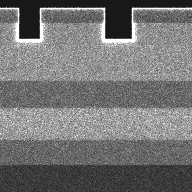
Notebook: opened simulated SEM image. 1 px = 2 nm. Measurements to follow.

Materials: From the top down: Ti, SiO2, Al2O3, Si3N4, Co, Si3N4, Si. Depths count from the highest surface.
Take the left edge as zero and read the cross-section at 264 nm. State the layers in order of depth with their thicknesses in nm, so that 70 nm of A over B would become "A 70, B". Ti 30, SiO2 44, Al2O3 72, Si3N4 54, Co 64, Si3N4 50, Si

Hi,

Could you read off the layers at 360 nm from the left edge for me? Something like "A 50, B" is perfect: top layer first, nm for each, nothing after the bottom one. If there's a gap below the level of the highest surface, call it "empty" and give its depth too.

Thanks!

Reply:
Ti 30, SiO2 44, Al2O3 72, Si3N4 54, Co 64, Si3N4 50, Si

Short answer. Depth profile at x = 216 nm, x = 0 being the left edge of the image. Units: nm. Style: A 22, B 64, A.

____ empty 62, SiO2 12, Al2O3 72, Si3N4 54, Co 64, Si3N4 50, Si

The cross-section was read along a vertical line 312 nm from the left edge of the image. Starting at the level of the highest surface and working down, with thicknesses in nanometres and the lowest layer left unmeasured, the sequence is Ti 30, SiO2 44, Al2O3 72, Si3N4 54, Co 64, Si3N4 50, Si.